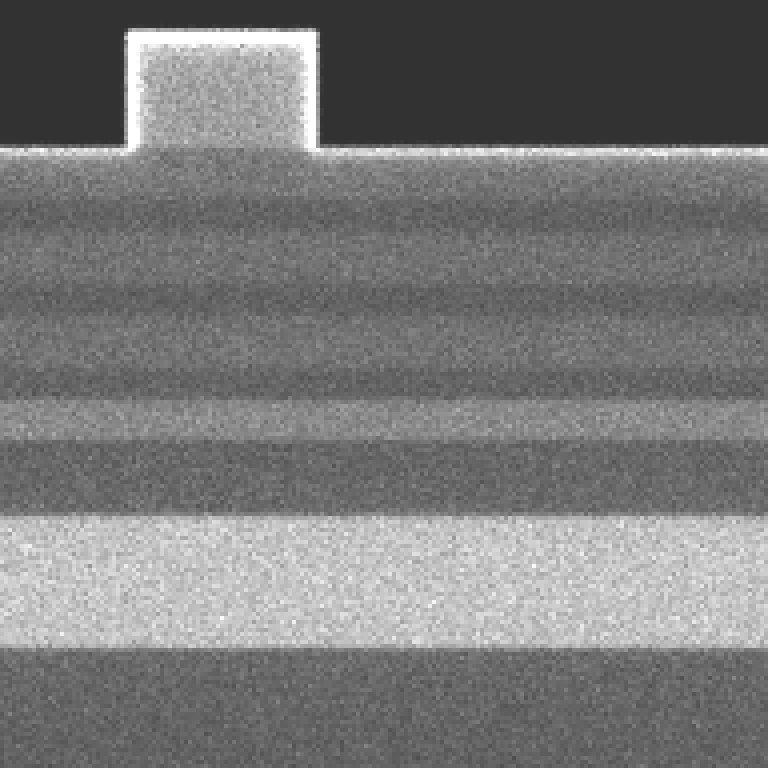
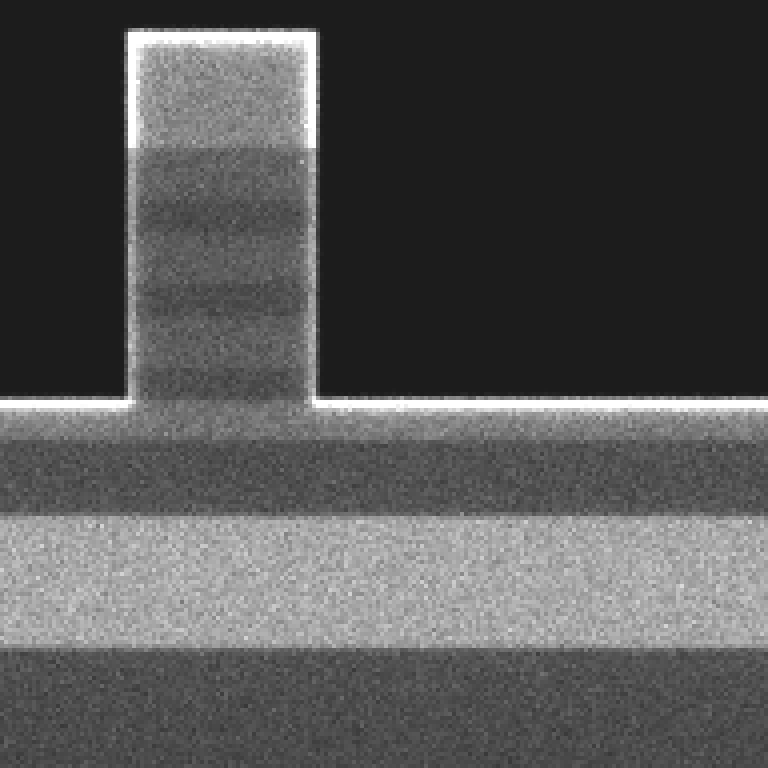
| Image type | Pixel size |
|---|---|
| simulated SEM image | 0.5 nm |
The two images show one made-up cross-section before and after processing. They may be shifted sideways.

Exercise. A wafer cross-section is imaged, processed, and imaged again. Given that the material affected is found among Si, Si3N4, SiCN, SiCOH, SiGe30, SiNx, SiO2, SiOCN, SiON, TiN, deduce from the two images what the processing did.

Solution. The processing removed Si and SiGe30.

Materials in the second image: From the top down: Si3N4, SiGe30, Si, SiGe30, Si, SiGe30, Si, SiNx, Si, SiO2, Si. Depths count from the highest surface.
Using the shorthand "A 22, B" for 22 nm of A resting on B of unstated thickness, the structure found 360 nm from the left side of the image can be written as empty 184, SiNx 20, Si 38, SiO2 66, Si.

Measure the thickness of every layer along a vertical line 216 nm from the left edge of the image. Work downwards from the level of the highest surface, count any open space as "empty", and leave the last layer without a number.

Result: empty 184, SiNx 20, Si 38, SiO2 66, Si